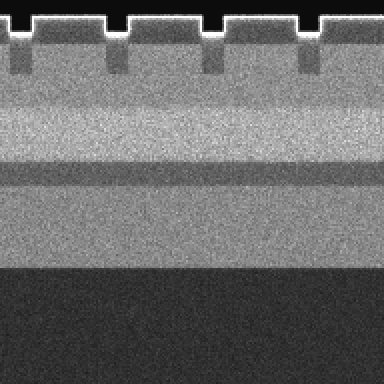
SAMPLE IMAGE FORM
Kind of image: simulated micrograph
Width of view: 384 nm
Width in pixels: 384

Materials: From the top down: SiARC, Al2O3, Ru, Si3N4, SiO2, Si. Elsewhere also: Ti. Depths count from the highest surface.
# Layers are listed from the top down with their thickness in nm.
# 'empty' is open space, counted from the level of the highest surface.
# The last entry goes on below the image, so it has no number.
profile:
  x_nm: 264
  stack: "Ti 28, Al2O3 64, Ru 54, Si3N4 24, SiO2 82, Si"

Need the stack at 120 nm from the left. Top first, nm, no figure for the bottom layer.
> empty 16, SiARC 42, Al2O3 34, Ru 54, Si3N4 24, SiO2 82, Si